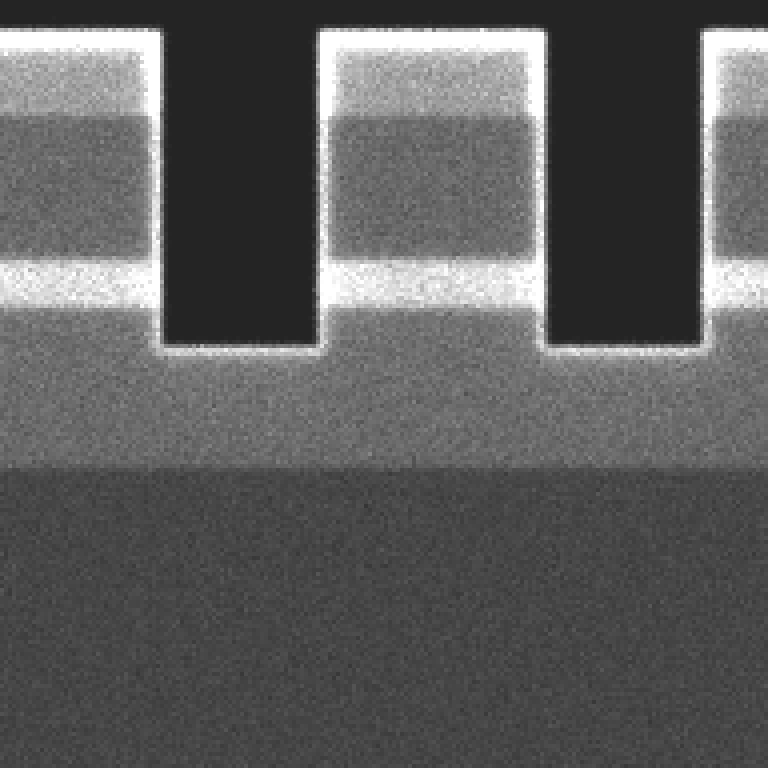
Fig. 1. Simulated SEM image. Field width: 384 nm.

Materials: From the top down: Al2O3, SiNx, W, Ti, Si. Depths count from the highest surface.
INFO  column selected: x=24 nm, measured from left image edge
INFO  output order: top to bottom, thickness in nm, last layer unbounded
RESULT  Al2O3 42, SiNx 72, W 24, Ti 80, Si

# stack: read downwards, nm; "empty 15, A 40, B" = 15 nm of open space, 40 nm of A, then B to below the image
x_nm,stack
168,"Al2O3 42, SiNx 72, W 24, Ti 80, Si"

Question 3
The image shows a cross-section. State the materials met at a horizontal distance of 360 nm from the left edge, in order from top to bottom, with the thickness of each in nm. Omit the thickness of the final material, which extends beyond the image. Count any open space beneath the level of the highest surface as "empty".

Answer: Al2O3 42, SiNx 72, W 24, Ti 80, Si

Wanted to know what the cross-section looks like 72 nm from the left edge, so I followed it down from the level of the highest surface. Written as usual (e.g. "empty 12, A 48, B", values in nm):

Al2O3 42, SiNx 72, W 24, Ti 80, Si